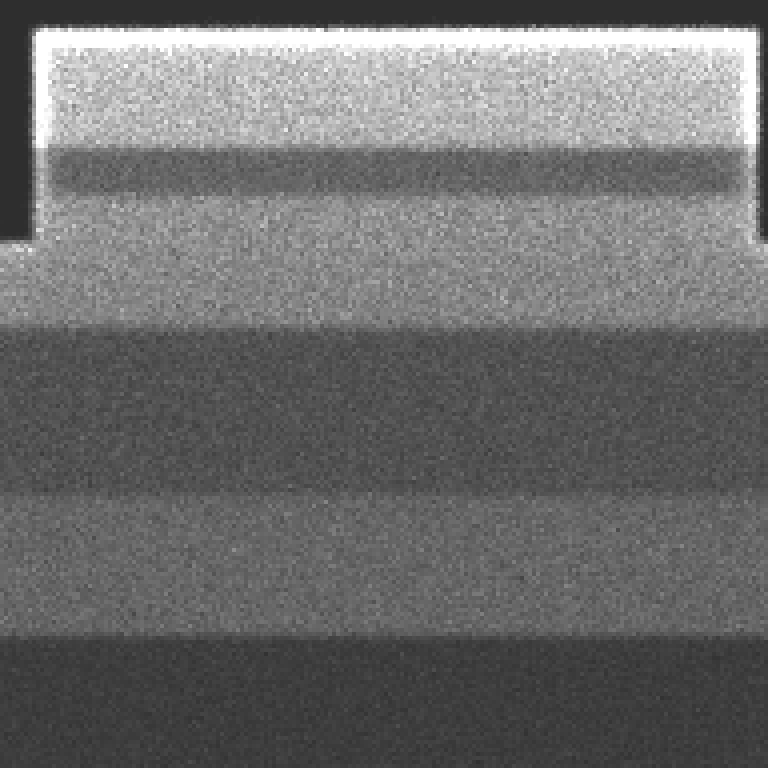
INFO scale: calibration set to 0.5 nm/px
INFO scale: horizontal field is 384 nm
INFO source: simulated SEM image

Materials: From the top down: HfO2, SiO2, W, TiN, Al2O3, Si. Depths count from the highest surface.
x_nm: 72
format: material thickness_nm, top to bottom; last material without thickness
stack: HfO2 58, SiO2 24, W 66, TiN 84, Al2O3 70, Si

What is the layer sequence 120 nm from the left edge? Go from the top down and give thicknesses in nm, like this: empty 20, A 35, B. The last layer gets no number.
HfO2 58, SiO2 24, W 66, TiN 84, Al2O3 70, Si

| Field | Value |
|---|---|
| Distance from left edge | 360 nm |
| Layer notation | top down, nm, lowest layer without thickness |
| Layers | HfO2 58, SiO2 24, W 66, TiN 84, Al2O3 70, Si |